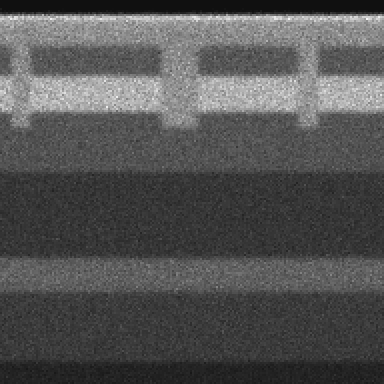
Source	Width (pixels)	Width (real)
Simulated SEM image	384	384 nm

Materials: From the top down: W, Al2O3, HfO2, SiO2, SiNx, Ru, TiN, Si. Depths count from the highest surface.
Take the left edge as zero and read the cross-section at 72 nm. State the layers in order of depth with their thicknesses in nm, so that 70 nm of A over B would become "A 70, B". W 30, Al2O3 30, HfO2 36, SiO2 60, SiNx 86, Ru 34, TiN 70, Si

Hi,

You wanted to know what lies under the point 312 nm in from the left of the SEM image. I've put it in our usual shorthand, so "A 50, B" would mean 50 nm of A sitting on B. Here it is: W 112, SiO2 44, SiNx 86, Ru 34, TiN 70, Si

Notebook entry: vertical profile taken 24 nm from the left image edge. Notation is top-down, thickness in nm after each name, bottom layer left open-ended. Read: W 112, SiO2 44, SiNx 86, Ru 34, TiN 70, Si